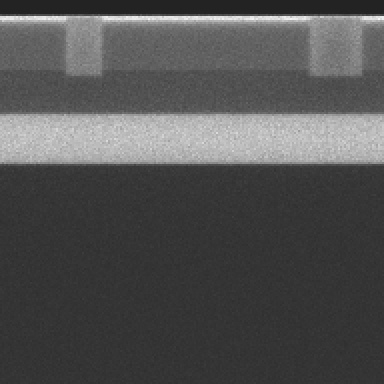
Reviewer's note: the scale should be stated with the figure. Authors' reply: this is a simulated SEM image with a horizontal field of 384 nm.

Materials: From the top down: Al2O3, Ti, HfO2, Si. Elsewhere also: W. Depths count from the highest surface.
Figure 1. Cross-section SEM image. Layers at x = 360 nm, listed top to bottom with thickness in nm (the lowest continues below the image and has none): W 60, Ti 38, HfO2 50, Si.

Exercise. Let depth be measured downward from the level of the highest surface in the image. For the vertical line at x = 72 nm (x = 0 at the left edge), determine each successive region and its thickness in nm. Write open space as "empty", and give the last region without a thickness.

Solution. W 60, Ti 38, HfO2 50, Si